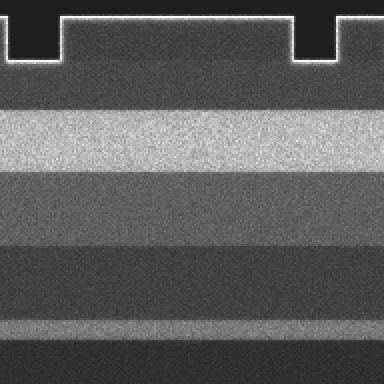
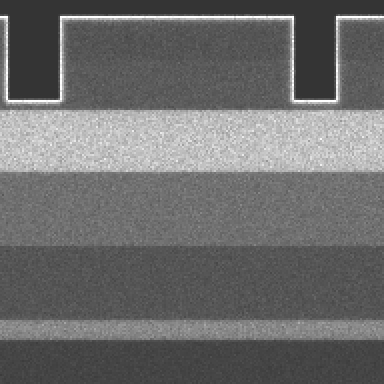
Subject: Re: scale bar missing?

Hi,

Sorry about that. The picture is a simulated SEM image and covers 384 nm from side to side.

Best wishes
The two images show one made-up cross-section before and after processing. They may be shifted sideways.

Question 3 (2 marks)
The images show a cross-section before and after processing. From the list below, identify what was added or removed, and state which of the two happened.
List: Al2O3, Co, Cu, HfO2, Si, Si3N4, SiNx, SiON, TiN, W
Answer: Si3N4 was removed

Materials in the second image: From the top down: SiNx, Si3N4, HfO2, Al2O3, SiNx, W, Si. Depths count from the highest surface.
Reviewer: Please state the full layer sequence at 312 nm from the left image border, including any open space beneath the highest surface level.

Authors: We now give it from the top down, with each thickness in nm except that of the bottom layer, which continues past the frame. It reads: empty 84, Si3N4 10, HfO2 62, Al2O3 74, SiNx 74, W 20, Si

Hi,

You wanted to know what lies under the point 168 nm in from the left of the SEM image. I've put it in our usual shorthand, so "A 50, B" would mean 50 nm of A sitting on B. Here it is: SiNx 44, Si3N4 50, HfO2 62, Al2O3 74, SiNx 74, W 20, Si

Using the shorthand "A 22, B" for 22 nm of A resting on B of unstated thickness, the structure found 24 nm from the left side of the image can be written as empty 84, Si3N4 10, HfO2 62, Al2O3 74, SiNx 74, W 20, Si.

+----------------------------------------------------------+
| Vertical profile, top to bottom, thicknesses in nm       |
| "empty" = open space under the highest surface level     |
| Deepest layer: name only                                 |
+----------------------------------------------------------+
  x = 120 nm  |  SiNx 44, Si3N4 50, HfO2 62, Al2O3 74, SiNx 74, W 20, Si